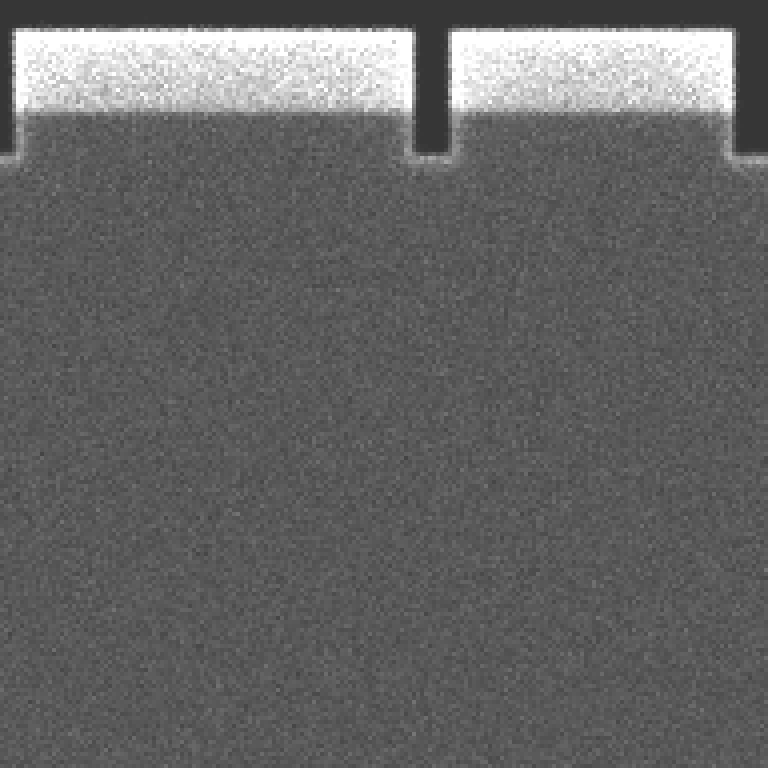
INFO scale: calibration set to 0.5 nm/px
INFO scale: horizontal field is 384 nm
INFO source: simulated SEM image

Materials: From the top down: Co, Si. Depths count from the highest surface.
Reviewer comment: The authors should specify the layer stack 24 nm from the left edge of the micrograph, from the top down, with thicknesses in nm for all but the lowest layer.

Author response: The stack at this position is Co 40, Si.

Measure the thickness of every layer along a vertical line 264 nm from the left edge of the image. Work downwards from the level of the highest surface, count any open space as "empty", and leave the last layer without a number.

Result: Co 40, Si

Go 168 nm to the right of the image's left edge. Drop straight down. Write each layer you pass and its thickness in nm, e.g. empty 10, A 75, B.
Co 40, Si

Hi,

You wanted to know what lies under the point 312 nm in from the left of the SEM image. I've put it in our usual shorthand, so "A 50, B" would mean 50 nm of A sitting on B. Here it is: Co 40, Si